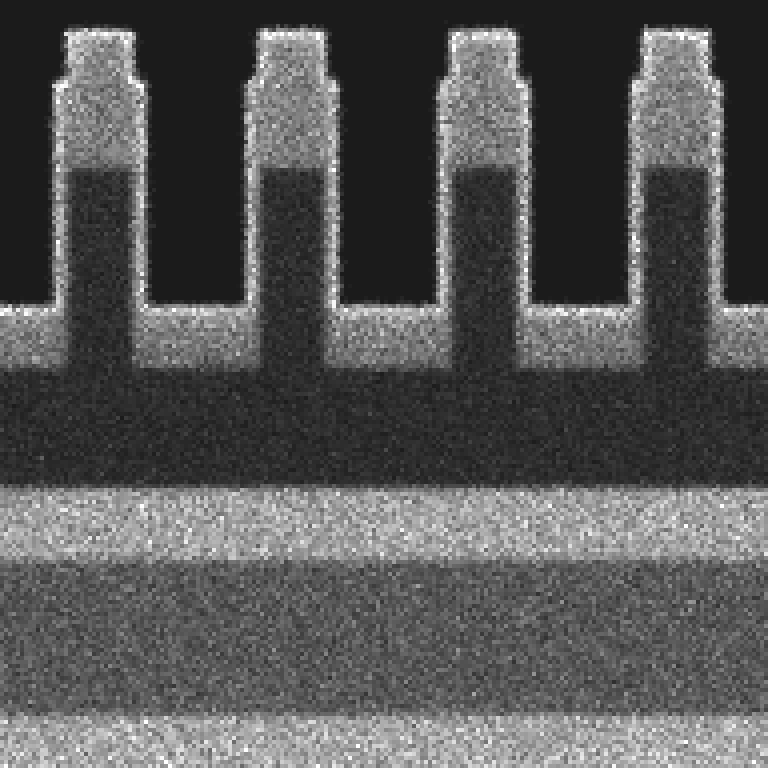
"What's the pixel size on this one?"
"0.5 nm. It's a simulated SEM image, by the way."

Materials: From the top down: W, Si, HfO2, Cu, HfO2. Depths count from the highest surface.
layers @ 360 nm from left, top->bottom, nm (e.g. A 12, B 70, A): empty 138, W 30, Si 60, HfO2 36, Cu 78, HfO2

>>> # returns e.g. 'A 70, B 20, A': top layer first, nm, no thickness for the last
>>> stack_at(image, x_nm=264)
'empty 138, W 30, Si 60, HfO2 36, Cu 78, HfO2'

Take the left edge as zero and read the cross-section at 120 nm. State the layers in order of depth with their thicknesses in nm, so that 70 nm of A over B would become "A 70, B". empty 138, W 30, Si 60, HfO2 36, Cu 78, HfO2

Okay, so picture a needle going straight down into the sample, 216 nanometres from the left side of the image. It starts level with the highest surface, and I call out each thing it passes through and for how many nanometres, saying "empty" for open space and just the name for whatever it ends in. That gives empty 138, W 30, Si 60, HfO2 36, Cu 78, HfO2